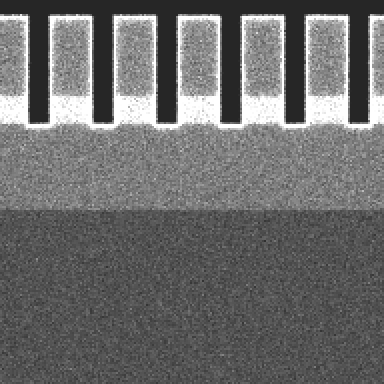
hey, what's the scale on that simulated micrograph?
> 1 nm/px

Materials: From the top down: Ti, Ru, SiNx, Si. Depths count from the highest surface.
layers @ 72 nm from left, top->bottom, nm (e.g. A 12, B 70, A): Ti 80, Ru 28, SiNx 86, Si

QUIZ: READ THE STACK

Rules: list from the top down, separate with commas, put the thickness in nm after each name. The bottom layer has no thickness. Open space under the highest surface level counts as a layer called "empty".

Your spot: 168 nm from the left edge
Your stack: empty 108, SiNx 86, Si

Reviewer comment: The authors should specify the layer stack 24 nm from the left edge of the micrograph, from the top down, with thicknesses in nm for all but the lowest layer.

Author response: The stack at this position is Ti 80, Ru 28, SiNx 86, Si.